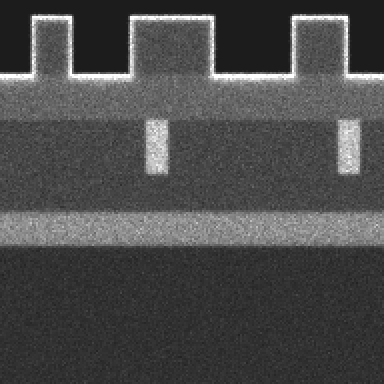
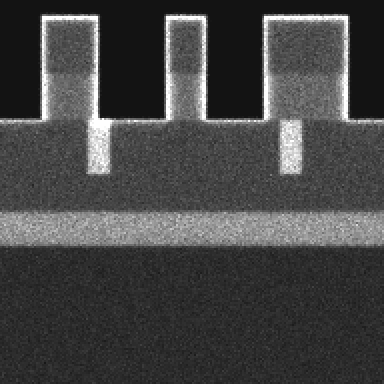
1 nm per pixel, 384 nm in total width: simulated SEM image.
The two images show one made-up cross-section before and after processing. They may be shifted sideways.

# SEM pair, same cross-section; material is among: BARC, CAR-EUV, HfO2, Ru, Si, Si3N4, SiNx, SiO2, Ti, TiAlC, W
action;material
removed;SiO2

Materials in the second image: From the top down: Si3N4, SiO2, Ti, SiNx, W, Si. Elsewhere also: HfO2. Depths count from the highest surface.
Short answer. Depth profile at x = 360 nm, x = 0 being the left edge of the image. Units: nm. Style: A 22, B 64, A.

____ empty 104, Ti 64, SiNx 28, W 34, Si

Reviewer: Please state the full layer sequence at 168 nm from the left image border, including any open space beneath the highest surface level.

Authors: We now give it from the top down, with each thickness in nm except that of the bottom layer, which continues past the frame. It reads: Si3N4 58, SiO2 46, Ti 64, SiNx 28, W 34, Si